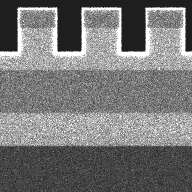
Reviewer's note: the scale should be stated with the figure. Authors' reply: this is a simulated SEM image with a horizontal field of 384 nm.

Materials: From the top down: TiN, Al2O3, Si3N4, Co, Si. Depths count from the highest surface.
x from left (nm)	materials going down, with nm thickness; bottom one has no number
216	TiN 40, Al2O3 84, Si3N4 86, Co 66, Si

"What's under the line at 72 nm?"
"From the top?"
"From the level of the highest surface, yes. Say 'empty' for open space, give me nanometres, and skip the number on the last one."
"TiN 40, Al2O3 84, Si3N4 86, Co 66, Si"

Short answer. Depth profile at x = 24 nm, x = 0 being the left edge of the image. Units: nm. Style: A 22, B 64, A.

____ empty 88, Al2O3 36, Si3N4 86, Co 66, Si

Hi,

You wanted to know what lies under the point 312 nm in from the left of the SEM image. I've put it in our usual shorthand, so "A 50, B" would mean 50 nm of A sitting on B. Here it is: TiN 40, Al2O3 84, Si3N4 86, Co 66, Si